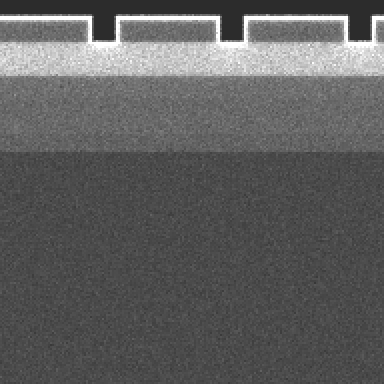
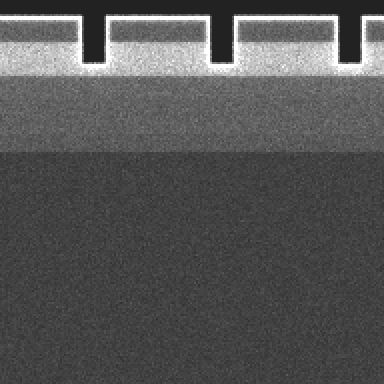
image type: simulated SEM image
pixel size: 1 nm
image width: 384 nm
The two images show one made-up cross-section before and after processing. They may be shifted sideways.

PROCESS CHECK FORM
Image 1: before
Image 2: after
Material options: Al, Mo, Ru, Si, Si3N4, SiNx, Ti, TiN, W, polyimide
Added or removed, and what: removed, W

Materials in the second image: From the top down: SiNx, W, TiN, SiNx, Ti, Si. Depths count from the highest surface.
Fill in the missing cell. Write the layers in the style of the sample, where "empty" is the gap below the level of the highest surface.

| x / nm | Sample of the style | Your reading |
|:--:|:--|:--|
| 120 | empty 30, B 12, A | SiNx 26, W 34, TiN 22, SiNx 36, Ti 18, Si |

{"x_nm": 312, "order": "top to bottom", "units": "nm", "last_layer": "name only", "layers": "SiNx 26, W 34, TiN 22, SiNx 36, Ti 18, Si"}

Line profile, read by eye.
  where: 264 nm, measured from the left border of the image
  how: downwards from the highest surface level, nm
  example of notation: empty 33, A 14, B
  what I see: SiNx 26, W 34, TiN 22, SiNx 36, Ti 18, Si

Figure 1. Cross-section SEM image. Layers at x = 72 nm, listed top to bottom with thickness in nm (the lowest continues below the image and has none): SiNx 26, W 34, TiN 22, SiNx 36, Ti 18, Si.